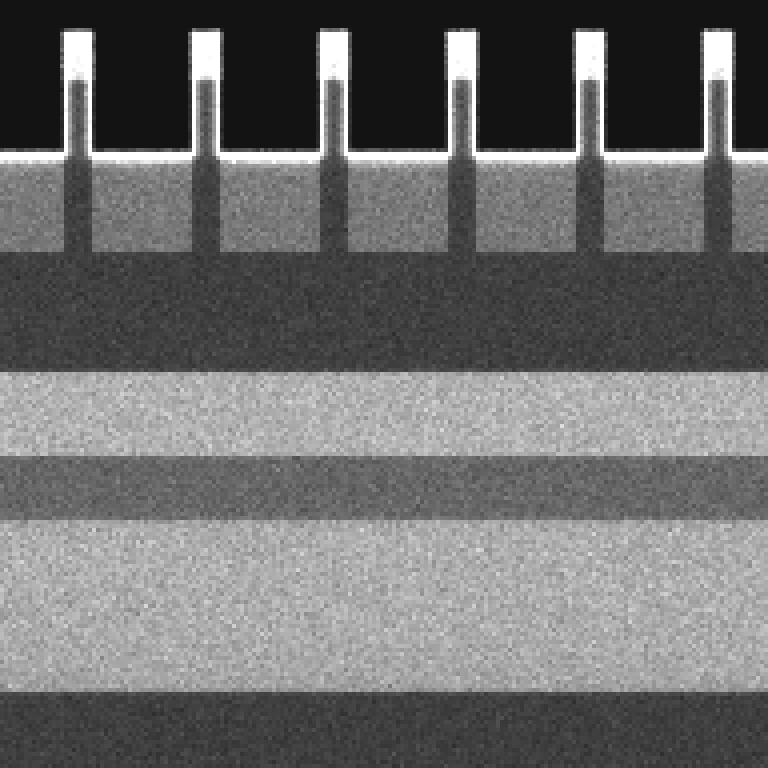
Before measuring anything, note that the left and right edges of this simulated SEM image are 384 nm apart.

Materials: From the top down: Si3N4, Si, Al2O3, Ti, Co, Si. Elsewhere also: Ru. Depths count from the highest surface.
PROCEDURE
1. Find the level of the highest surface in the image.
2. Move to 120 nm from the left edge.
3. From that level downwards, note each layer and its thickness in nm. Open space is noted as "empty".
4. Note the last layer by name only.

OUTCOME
empty 60, Si3N4 50, Si 60, Al2O3 42, Ti 32, Co 86, Si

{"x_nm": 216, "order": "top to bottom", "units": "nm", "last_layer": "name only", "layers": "empty 60, Si3N4 50, Si 60, Al2O3 42, Ti 32, Co 86, Si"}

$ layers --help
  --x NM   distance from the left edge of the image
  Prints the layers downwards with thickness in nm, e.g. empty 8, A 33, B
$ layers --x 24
empty 60, Si3N4 50, Si 60, Al2O3 42, Ti 32, Co 86, Si